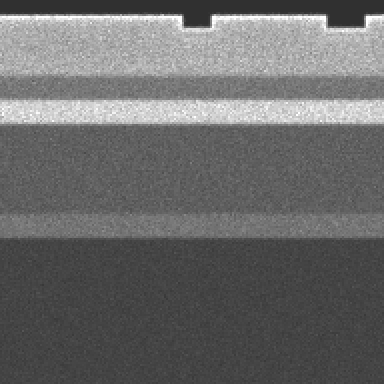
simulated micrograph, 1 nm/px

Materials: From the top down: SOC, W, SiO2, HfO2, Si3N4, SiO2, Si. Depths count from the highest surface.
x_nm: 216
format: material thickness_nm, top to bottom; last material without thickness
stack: W 60, SiO2 24, HfO2 24, Si3N4 90, SiO2 24, Si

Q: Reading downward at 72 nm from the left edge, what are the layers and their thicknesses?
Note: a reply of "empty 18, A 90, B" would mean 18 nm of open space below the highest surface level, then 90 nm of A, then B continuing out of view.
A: W 60, SiO2 24, HfO2 24, Si3N4 90, SiO2 24, Si